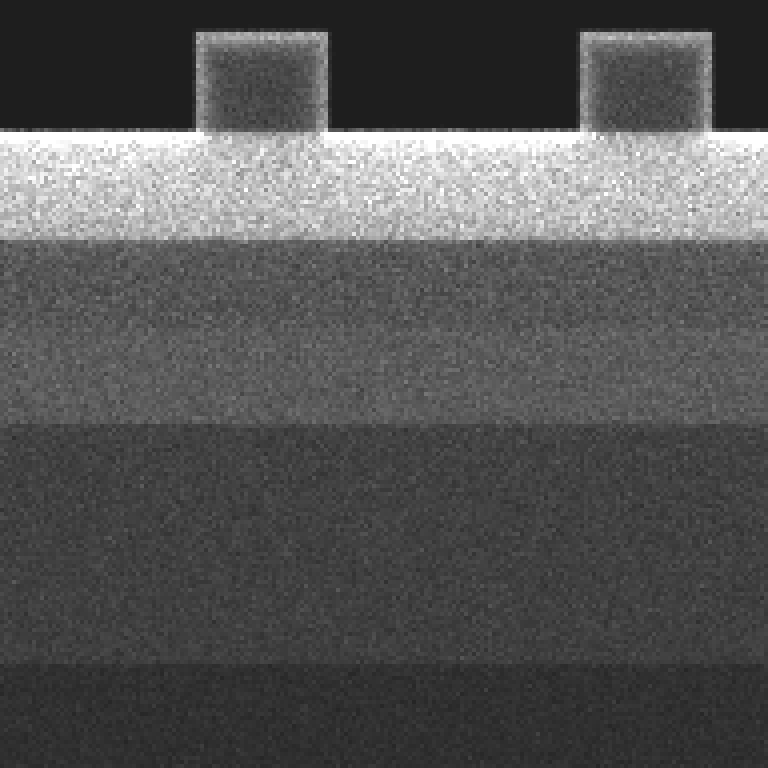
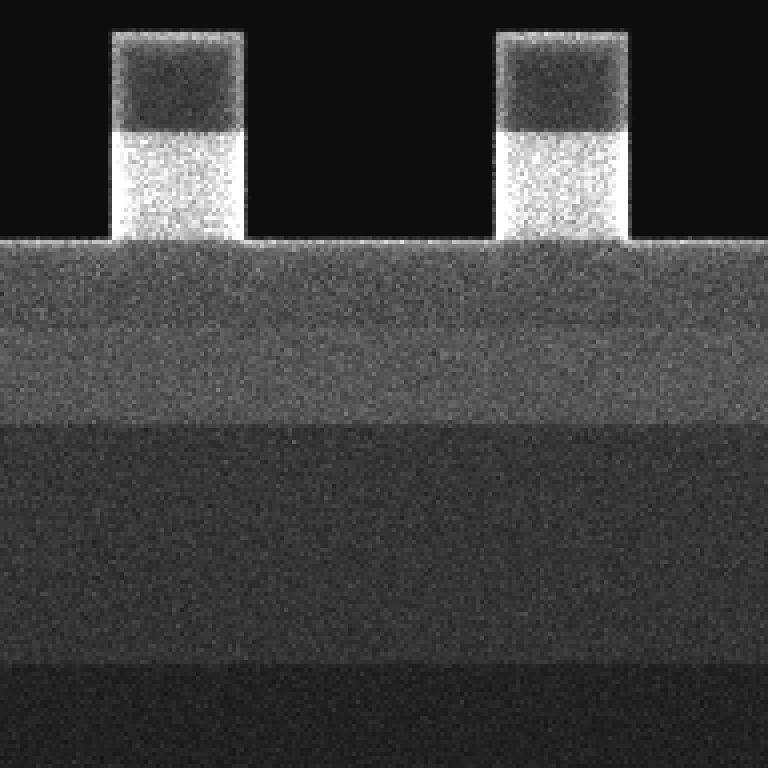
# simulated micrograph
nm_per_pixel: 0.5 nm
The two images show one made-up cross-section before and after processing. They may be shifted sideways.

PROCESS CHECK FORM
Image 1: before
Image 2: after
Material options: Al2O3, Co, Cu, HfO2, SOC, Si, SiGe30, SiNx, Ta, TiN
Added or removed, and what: removed, HfO2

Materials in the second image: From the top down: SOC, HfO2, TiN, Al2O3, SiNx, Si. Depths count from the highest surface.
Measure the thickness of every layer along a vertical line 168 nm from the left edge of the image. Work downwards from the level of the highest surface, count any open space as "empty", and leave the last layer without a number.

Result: empty 104, TiN 44, Al2O3 48, SiNx 120, Si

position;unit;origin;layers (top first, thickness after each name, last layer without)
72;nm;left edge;SOC 50, HfO2 54, TiN 44, Al2O3 48, SiNx 120, Si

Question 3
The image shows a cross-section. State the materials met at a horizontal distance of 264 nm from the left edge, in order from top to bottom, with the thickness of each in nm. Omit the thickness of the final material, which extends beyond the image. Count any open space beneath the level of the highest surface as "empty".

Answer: SOC 50, HfO2 54, TiN 44, Al2O3 48, SiNx 120, Si